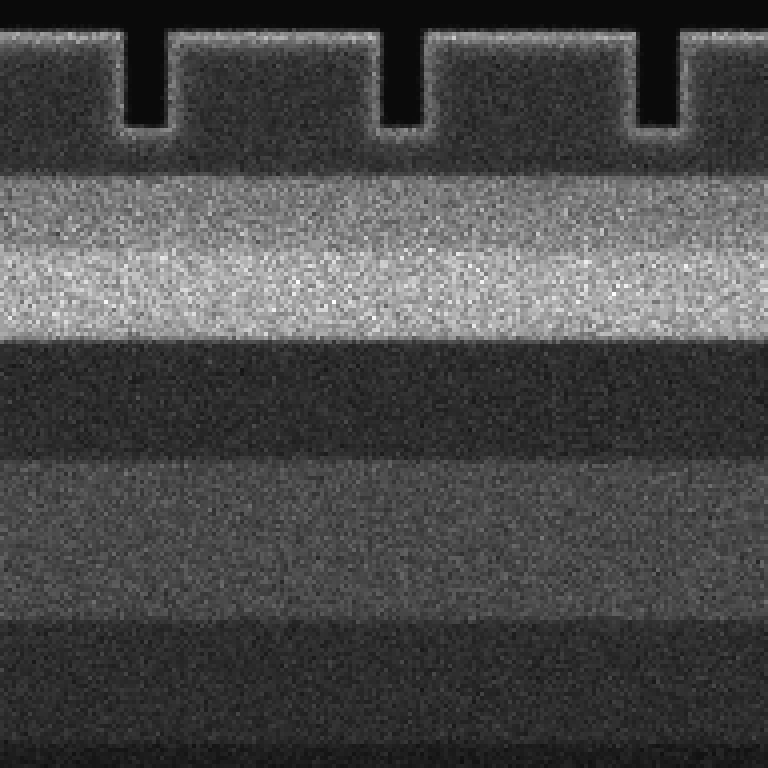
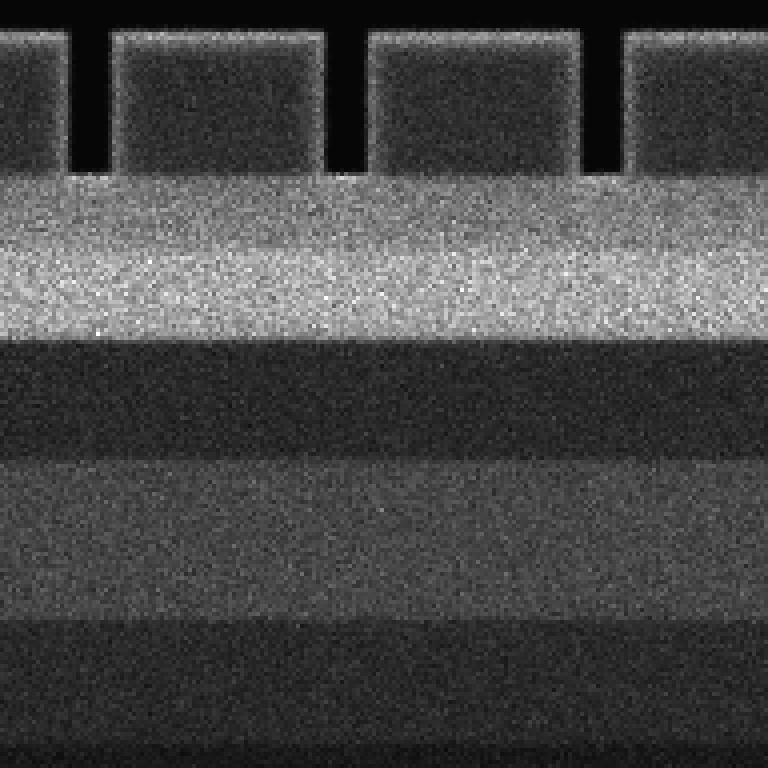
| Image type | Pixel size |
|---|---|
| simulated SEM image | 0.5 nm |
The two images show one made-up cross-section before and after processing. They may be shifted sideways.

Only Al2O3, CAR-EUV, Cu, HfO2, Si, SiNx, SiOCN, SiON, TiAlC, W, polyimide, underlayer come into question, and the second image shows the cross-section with underlayer removed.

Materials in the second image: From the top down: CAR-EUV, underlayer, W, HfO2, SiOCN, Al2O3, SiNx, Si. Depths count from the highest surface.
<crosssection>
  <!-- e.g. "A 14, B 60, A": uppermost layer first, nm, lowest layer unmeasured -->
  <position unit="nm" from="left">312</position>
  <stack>CAR-EUV 48, underlayer 24, W 38, HfO2 44, SiOCN 60, Al2O3 80, SiNx 62, Si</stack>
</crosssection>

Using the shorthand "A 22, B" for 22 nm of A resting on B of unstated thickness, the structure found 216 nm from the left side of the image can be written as CAR-EUV 48, underlayer 24, W 38, HfO2 44, SiOCN 60, Al2O3 80, SiNx 62, Si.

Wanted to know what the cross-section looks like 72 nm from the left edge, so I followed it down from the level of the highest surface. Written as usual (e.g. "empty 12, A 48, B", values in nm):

CAR-EUV 48, underlayer 24, W 38, HfO2 44, SiOCN 60, Al2O3 80, SiNx 62, Si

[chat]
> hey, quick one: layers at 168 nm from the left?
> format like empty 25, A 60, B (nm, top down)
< empty 72, W 38, HfO2 44, SiOCN 60, Al2O3 80, SiNx 62, Si